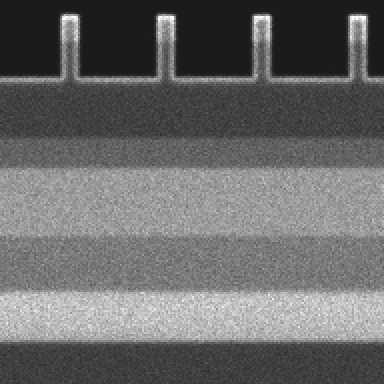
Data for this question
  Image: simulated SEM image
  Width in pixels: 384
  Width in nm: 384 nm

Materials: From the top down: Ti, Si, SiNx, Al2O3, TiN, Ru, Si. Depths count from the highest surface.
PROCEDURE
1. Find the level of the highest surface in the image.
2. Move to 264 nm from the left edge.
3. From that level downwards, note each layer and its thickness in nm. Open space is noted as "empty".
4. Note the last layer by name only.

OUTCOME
Ti 26, Si 96, SiNx 30, Al2O3 68, TiN 56, Ru 50, Si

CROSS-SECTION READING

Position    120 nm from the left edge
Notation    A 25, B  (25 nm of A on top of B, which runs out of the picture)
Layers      empty 62, Si 60, SiNx 30, Al2O3 68, TiN 56, Ru 50, Si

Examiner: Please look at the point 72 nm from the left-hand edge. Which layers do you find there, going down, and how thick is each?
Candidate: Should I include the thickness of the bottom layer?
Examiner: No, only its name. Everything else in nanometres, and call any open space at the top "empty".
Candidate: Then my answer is Ti 26, Si 96, SiNx 30, Al2O3 68, TiN 56, Ru 50, Si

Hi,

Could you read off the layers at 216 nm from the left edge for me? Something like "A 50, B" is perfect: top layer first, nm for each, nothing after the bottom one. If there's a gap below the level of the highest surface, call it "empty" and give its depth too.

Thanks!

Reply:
empty 62, Si 60, SiNx 30, Al2O3 68, TiN 56, Ru 50, Si